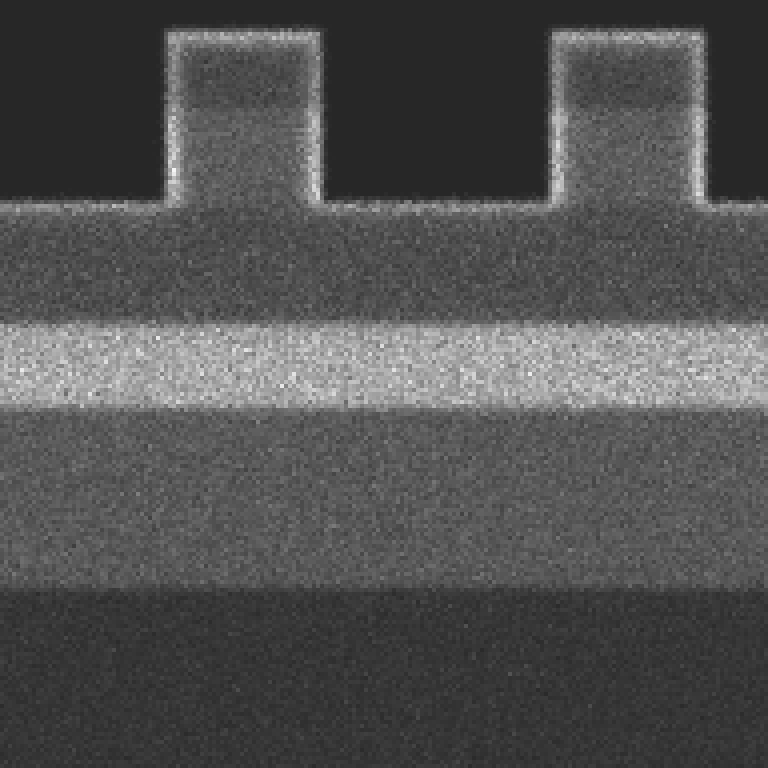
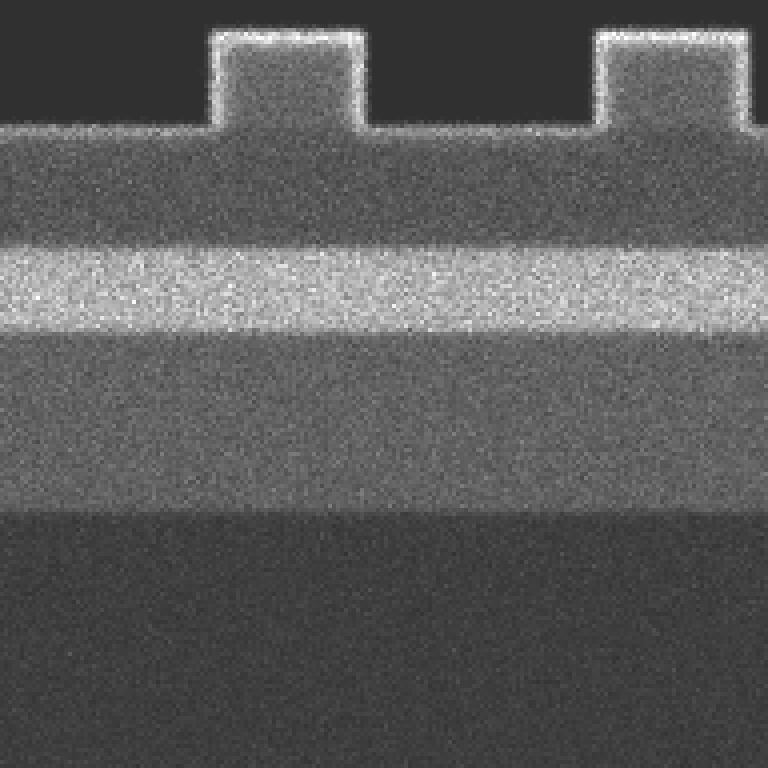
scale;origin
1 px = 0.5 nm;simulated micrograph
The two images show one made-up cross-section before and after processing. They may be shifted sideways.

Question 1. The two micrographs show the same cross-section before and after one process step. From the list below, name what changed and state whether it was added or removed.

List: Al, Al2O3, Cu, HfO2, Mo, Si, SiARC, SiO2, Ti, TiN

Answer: SiARC, removed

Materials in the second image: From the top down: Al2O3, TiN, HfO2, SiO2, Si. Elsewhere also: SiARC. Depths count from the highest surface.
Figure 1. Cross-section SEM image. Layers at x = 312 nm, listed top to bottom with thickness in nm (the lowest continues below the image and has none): Al2O3 48, TiN 60, HfO2 42, SiO2 90, Si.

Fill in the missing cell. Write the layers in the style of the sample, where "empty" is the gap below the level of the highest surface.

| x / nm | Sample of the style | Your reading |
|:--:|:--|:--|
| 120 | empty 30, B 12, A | Al2O3 48, TiN 60, HfO2 42, SiO2 90, Si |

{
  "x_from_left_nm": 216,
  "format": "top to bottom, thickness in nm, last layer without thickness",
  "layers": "empty 48, TiN 60, HfO2 42, SiO2 90, Si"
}